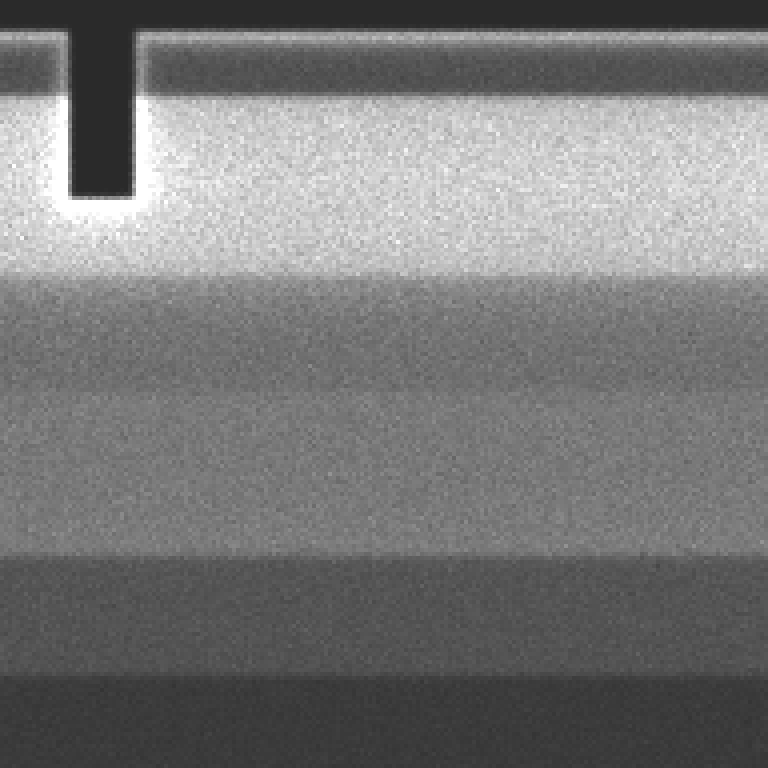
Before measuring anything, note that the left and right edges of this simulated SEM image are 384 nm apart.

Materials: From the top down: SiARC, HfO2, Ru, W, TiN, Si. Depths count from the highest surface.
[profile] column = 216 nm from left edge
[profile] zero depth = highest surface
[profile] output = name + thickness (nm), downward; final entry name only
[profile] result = SiARC 32, HfO2 90, Ru 58, W 82, TiN 60, Si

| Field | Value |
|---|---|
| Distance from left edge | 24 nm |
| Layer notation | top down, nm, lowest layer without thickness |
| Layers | SiARC 32, HfO2 90, Ru 58, W 82, TiN 60, Si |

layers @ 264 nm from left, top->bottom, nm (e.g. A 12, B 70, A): SiARC 32, HfO2 90, Ru 58, W 82, TiN 60, Si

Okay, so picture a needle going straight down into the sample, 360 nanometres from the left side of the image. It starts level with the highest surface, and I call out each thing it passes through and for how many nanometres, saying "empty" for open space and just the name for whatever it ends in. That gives SiARC 32, HfO2 90, Ru 58, W 82, TiN 60, Si